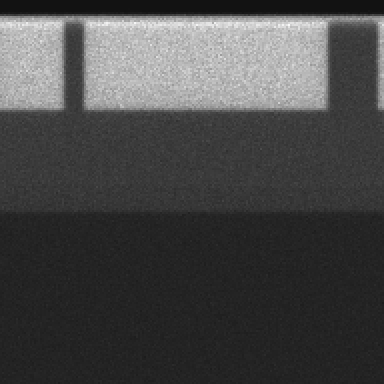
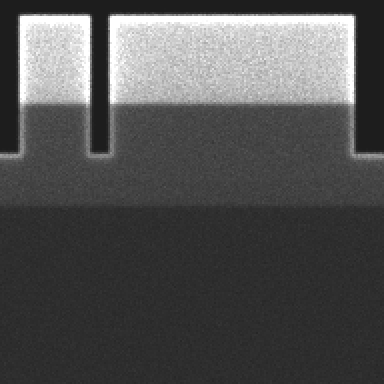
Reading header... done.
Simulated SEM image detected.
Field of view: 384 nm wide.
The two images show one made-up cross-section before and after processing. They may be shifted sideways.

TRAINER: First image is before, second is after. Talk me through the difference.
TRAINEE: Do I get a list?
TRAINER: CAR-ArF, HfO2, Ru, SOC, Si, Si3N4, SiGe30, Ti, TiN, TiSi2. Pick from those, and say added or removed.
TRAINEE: removed: SOC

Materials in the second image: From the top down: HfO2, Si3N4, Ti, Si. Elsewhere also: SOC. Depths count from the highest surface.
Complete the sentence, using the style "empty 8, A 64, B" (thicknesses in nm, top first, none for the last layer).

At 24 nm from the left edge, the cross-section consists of HfO2 88, Si3N4 76, Ti 26, Si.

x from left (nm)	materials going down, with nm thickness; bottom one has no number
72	HfO2 88, Si3N4 76, Ti 26, Si